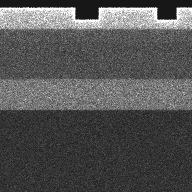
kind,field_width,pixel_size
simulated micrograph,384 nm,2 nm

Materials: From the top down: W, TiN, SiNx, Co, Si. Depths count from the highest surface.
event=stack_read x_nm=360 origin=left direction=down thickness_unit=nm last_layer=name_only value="W 42, TiN 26, SiNx 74, Co 62, Si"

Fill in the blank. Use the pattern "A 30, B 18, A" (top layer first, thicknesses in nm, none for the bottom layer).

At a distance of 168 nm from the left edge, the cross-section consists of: empty 24, W 18, TiN 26, SiNx 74, Co 62, Si